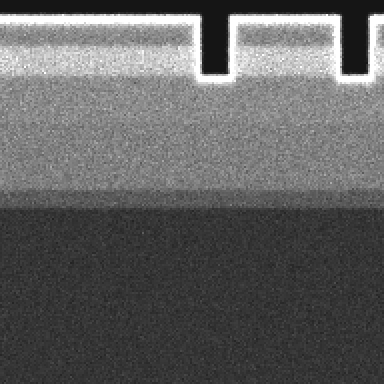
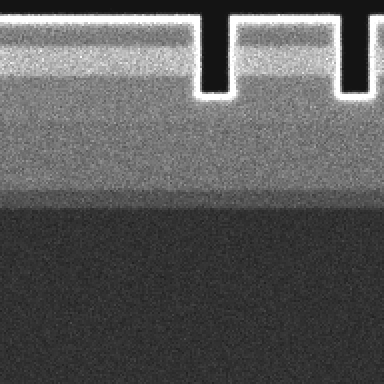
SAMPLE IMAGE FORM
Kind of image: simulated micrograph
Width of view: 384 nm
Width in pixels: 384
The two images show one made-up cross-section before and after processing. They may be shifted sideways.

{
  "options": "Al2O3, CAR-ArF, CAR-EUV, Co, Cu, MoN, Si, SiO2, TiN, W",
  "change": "removed",
  "material": "Al2O3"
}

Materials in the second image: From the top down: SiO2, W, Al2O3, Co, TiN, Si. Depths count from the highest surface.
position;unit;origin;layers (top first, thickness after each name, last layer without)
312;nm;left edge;SiO2 30, W 30, Al2O3 46, Co 68, TiN 18, Si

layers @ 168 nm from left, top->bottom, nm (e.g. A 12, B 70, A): SiO2 30, W 30, Al2O3 46, Co 68, TiN 18, Si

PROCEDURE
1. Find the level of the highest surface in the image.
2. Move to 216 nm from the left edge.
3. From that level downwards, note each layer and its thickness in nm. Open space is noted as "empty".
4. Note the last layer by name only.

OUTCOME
empty 78, Al2O3 28, Co 68, TiN 18, Si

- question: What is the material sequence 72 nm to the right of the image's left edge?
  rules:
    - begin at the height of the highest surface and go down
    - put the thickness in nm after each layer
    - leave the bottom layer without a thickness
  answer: SiO2 30, W 30, Al2O3 46, Co 68, TiN 18, Si